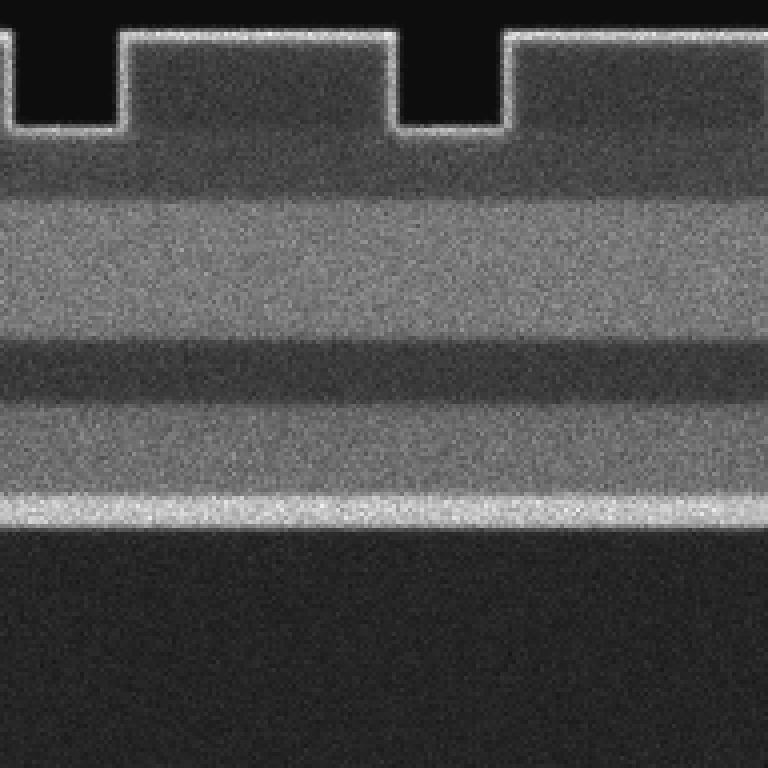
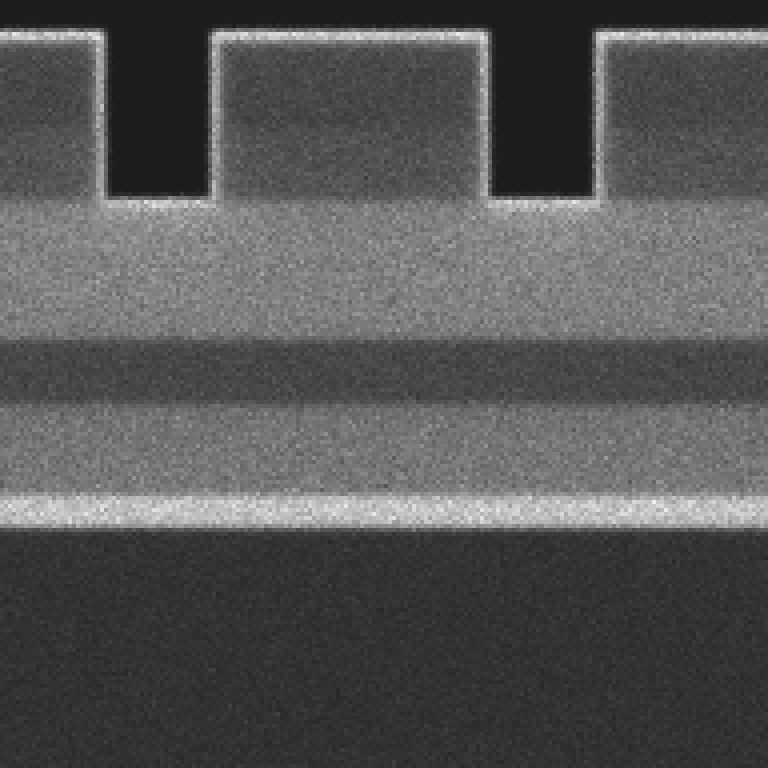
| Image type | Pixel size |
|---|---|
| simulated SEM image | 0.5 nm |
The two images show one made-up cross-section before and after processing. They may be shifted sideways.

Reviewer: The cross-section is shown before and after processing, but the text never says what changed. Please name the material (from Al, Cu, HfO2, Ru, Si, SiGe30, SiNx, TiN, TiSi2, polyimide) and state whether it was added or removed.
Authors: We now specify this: TiN, removed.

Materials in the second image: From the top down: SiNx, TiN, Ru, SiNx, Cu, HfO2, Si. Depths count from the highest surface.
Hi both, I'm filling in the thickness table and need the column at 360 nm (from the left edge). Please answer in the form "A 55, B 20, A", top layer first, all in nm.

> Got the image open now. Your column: SiNx 48, TiN 36, Ru 70, SiNx 32, Cu 46, HfO2 16, Si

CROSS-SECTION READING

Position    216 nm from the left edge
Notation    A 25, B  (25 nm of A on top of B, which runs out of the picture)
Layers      SiNx 48, TiN 36, Ru 70, SiNx 32, Cu 46, HfO2 16, Si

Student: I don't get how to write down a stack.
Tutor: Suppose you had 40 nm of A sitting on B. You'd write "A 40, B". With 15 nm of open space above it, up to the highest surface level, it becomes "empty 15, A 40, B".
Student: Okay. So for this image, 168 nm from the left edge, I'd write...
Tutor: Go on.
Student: SiNx 48, TiN 36, Ru 70, SiNx 32, Cu 46, HfO2 16, Si